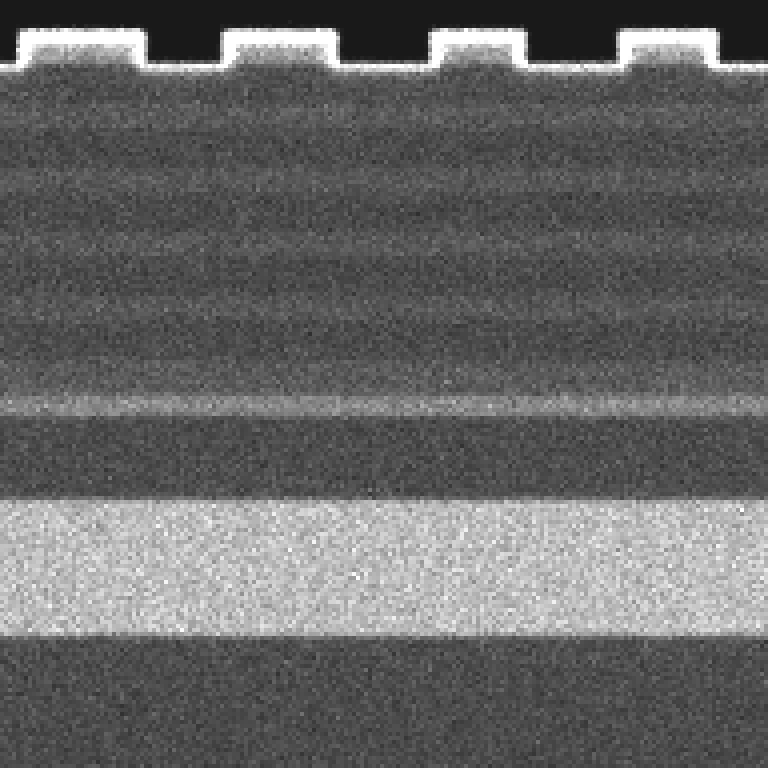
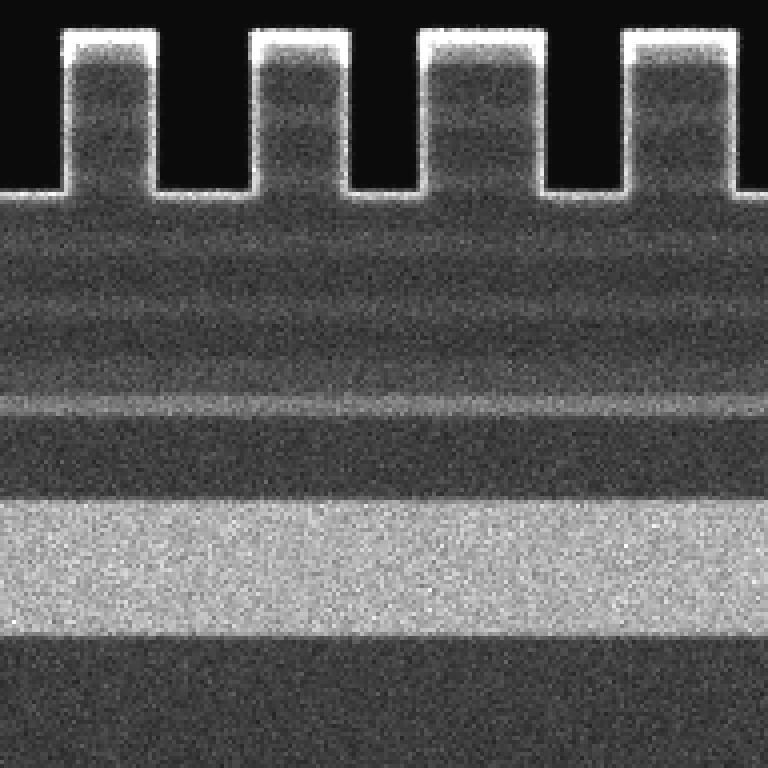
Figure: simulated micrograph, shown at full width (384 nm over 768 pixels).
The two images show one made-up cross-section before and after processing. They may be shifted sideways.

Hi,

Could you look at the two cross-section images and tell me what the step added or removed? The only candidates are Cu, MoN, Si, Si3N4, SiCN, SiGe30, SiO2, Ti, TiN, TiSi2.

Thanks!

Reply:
removed Si and SiGe30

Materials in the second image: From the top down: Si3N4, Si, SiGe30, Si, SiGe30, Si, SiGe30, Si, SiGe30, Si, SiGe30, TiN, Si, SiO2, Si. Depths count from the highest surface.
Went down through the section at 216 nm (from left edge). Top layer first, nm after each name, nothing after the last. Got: Si3N4 16, Si 20, SiGe30 12, Si 20, SiGe30 12, Si 20, SiGe30 12, Si 20, SiGe30 12, Si 20, SiGe30 18, TiN 10, Si 42, SiO2 68, Si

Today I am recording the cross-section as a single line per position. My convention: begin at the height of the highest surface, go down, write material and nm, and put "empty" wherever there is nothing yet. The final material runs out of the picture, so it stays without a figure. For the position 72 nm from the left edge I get Si3N4 16, Si 20, SiGe30 12, Si 20, SiGe30 12, Si 20, SiGe30 12, Si 20, SiGe30 12, Si 20, SiGe30 18, TiN 10, Si 42, SiO2 68, Si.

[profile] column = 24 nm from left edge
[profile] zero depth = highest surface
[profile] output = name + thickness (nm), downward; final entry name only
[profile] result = empty 80, Si 20, SiGe30 12, Si 20, SiGe30 12, Si 20, SiGe30 18, TiN 10, Si 42, SiO2 68, Si